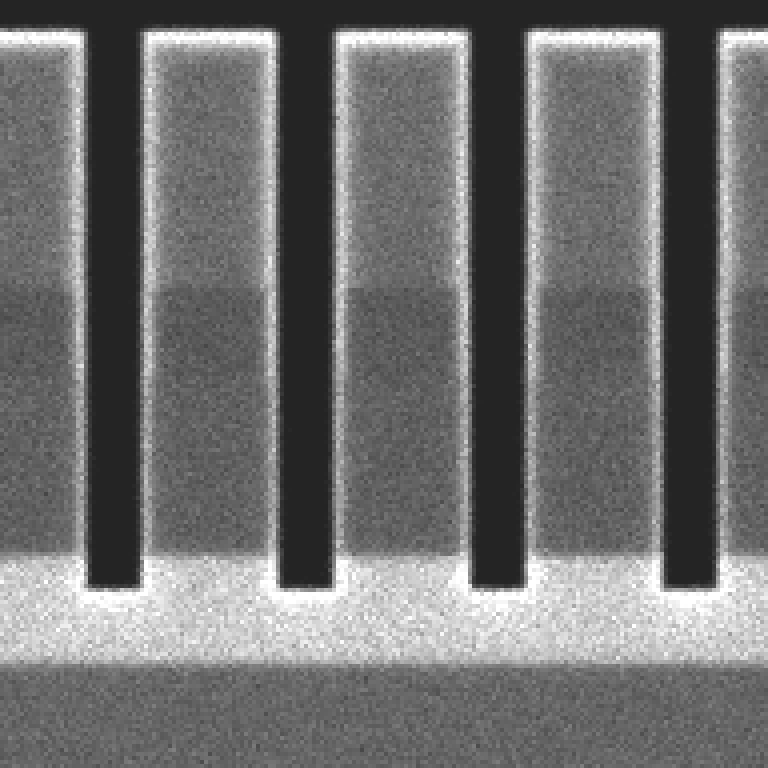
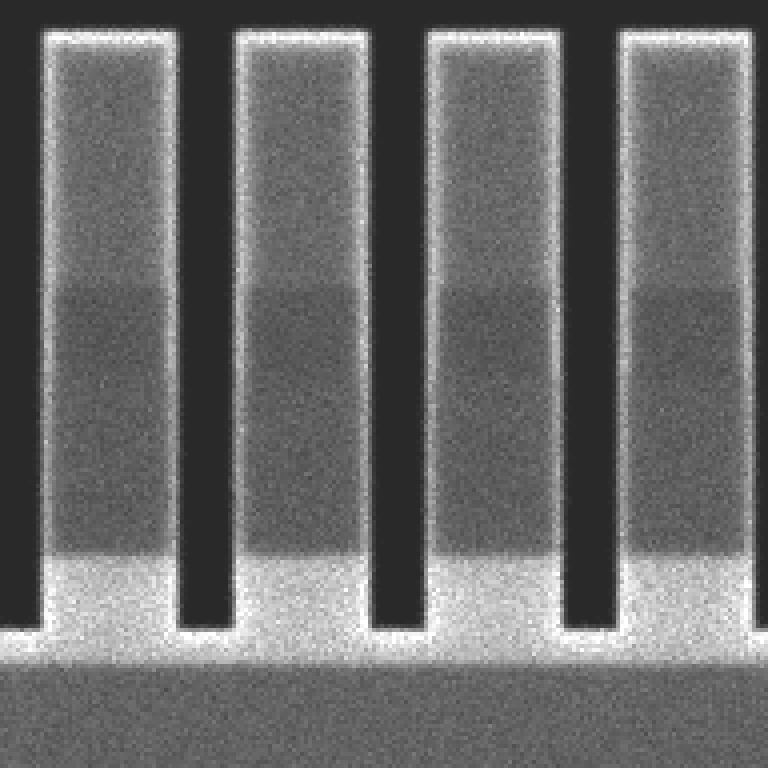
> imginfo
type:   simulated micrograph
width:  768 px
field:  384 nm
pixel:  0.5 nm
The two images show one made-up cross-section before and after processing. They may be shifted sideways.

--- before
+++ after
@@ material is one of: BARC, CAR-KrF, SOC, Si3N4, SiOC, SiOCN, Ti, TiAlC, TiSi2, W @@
W removed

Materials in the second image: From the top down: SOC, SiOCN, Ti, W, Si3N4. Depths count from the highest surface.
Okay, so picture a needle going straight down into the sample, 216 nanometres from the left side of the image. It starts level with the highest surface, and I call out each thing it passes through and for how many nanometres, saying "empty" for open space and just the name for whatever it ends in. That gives SOC 128, SiOCN 44, Ti 90, W 54, Si3N4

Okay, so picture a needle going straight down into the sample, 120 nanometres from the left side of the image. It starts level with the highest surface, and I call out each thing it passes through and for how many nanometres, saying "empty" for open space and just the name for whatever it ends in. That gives SOC 128, SiOCN 44, Ti 90, W 54, Si3N4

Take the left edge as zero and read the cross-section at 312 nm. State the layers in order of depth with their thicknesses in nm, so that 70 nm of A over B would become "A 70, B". SOC 128, SiOCN 44, Ti 90, W 54, Si3N4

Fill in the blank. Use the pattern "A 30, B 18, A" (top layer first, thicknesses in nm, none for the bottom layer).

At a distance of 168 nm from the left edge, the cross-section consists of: SOC 128, SiOCN 44, Ti 90, W 54, Si3N4